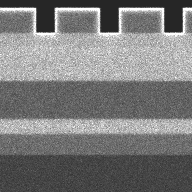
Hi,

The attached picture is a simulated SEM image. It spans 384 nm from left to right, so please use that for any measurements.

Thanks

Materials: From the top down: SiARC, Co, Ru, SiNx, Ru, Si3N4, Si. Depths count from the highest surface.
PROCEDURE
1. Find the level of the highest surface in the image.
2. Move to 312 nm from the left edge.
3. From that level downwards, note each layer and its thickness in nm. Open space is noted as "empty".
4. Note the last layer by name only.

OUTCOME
SiARC 50, Co 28, Ru 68, SiNx 76, Ru 30, Si3N4 42, Si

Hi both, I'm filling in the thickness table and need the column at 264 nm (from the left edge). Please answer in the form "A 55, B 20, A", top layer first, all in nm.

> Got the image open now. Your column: SiARC 50, Co 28, Ru 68, SiNx 76, Ru 30, Si3N4 42, Si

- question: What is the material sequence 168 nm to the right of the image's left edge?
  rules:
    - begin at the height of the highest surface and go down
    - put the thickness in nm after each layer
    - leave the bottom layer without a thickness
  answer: SiARC 50, Co 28, Ru 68, SiNx 76, Ru 30, Si3N4 42, Si